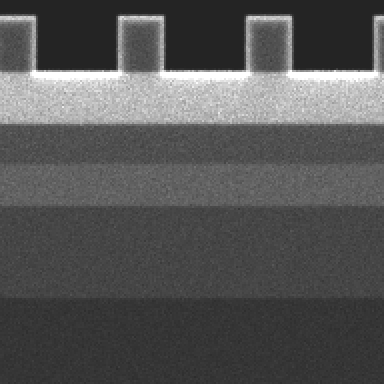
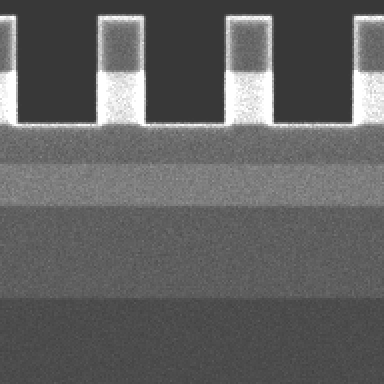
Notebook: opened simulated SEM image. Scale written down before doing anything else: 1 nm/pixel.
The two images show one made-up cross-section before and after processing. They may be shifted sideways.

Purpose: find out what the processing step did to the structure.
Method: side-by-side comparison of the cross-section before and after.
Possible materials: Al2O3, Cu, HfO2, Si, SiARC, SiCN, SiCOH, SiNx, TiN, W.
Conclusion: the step removed HfO2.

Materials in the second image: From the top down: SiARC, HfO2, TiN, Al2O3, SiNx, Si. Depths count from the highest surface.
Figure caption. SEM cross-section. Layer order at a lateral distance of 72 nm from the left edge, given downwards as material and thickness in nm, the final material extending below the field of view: empty 108, TiN 40, Al2O3 42, SiNx 92, Si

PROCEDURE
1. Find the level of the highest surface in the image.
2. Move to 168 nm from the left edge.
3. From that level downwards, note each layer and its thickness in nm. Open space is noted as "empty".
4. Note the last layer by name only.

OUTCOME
empty 108, TiN 40, Al2O3 42, SiNx 92, Si